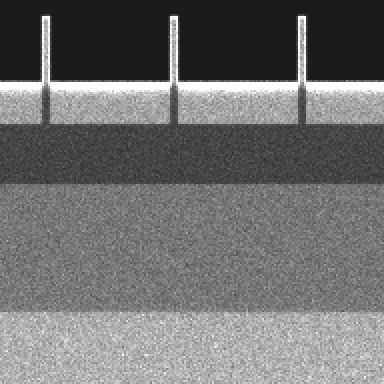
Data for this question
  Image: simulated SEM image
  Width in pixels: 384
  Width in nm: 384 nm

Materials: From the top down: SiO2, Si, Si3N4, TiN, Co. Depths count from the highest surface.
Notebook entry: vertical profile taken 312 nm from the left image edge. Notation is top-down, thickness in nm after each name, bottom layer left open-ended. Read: empty 66, SiO2 42, Si 60, Si3N4 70, TiN 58, Co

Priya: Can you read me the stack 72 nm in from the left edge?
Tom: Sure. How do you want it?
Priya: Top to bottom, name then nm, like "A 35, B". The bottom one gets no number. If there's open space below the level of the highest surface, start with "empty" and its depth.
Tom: empty 66, SiO2 42, Si 60, Si3N4 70, TiN 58, Co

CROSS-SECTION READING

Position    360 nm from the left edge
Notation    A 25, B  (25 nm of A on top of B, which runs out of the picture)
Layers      empty 66, SiO2 42, Si 60, Si3N4 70, TiN 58, Co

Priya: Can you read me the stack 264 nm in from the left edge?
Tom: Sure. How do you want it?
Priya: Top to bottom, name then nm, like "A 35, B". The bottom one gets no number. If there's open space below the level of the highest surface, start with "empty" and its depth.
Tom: empty 66, SiO2 42, Si 60, Si3N4 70, TiN 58, Co